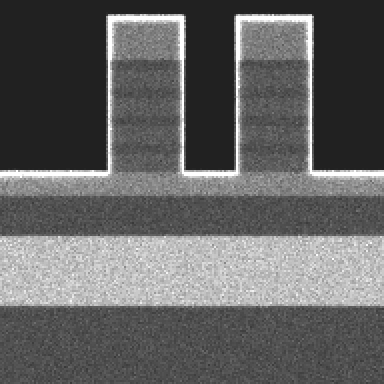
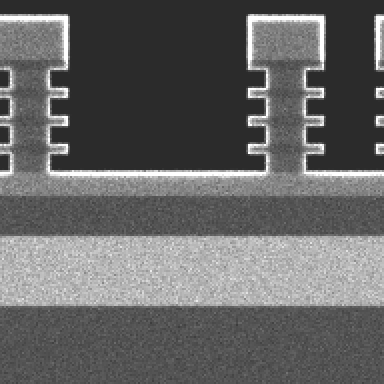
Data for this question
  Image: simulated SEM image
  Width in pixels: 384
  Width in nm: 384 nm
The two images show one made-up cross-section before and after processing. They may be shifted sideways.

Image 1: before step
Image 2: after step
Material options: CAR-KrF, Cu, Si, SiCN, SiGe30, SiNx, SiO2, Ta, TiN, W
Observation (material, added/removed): SiGe30, removed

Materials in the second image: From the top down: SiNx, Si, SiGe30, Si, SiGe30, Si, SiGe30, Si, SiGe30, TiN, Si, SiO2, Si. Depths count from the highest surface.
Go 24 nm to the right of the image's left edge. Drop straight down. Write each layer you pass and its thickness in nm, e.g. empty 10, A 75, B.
SiNx 44, Si 10, SiGe30 18, Si 10, SiGe30 18, Si 10, SiGe30 18, Si 10, SiGe30 18, TiN 24, Si 40, SiO2 70, Si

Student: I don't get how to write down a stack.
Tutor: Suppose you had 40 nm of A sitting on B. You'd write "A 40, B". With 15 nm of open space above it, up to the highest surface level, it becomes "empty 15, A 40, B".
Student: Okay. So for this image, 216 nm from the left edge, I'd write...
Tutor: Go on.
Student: empty 156, TiN 24, Si 40, SiO2 70, Si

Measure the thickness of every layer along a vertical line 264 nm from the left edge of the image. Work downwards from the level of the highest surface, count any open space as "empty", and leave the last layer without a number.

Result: SiNx 44, Si 10, empty 18, Si 10, empty 18, Si 10, empty 18, Si 10, empty 18, TiN 24, Si 40, SiO2 70, Si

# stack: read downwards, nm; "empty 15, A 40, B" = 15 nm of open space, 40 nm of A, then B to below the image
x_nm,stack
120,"empty 156, TiN 24, Si 40, SiO2 70, Si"